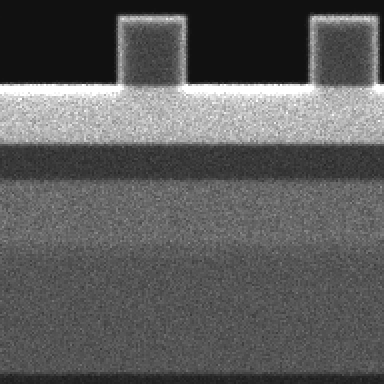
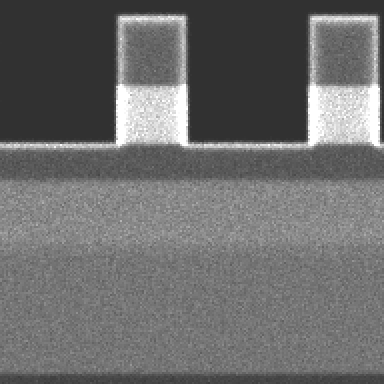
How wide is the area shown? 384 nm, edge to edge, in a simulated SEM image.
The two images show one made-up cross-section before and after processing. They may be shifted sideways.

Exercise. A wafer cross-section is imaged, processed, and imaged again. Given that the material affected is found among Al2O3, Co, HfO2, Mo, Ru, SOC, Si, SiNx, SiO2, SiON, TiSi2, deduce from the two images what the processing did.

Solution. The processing removed HfO2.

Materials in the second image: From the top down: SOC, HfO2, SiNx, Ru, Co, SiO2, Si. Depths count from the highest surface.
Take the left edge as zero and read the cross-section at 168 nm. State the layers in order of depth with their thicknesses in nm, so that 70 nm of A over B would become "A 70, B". SOC 70, HfO2 58, SiNx 36, Ru 64, Co 12, SiO2 118, Si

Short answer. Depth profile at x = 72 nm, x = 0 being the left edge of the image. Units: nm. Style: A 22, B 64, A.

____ empty 128, SiNx 36, Ru 64, Co 12, SiO2 118, Si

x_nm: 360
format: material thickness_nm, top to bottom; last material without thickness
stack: SOC 70, HfO2 58, SiNx 36, Ru 64, Co 12, SiO2 118, Si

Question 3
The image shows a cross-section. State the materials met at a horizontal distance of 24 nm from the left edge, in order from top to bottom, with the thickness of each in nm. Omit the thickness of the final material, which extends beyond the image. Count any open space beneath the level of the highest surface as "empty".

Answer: empty 128, SiNx 36, Ru 64, Co 12, SiO2 118, Si